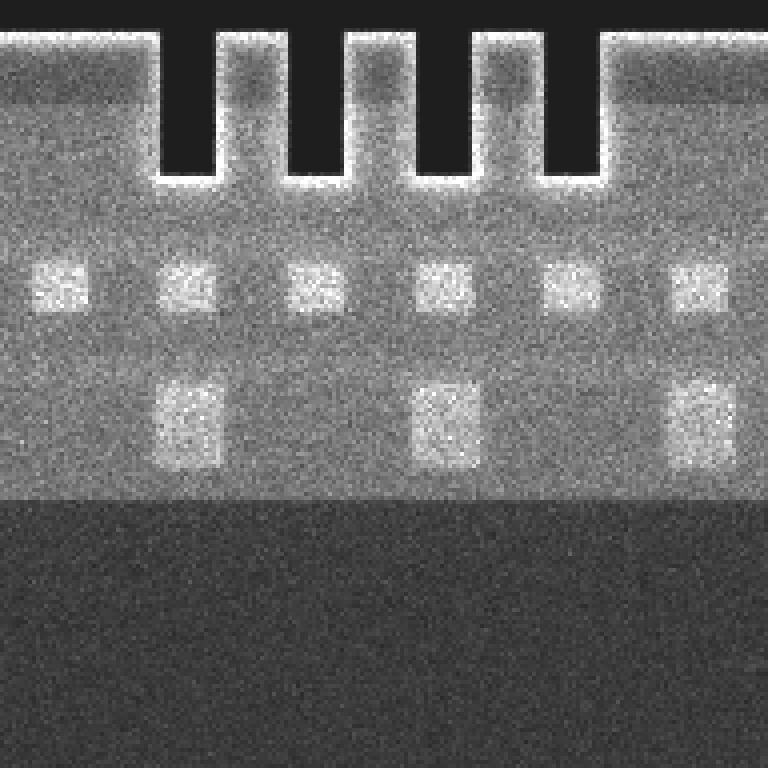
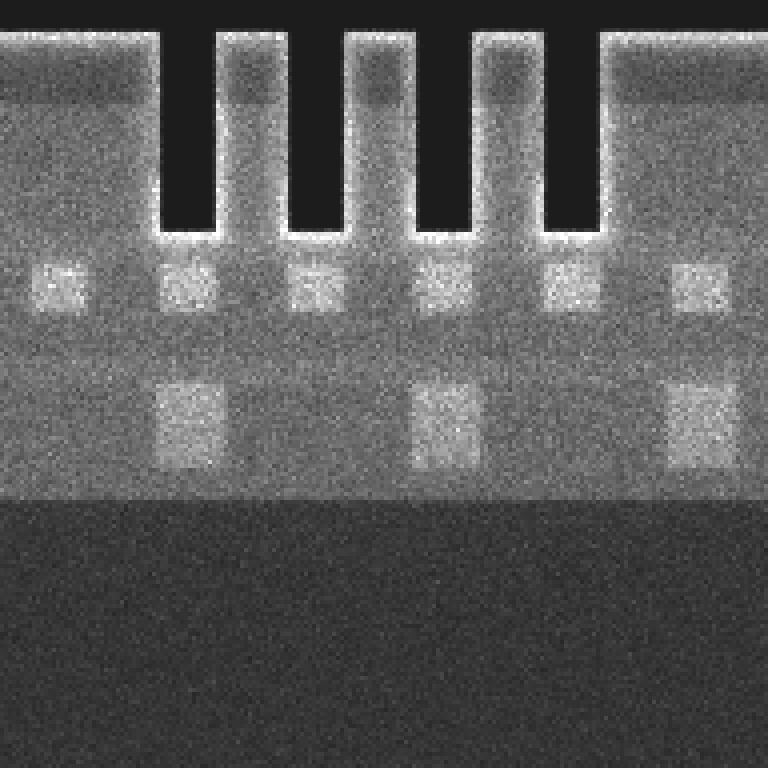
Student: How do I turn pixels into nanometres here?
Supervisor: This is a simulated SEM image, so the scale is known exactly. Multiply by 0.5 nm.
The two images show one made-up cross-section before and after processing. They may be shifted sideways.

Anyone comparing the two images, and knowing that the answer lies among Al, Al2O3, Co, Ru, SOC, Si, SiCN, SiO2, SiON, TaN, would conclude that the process removed SiO2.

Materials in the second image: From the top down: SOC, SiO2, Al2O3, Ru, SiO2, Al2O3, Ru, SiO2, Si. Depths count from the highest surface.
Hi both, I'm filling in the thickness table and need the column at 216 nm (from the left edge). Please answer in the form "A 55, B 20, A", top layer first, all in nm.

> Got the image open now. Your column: empty 100, Al2O3 16, Ru 24, SiO2 22, Al2O3 14, Ru 42, SiO2 16, Si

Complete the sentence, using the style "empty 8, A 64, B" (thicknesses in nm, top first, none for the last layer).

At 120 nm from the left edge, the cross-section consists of SOC 36, SiO2 64, Al2O3 16, SiO2 46, Al2O3 14, SiO2 58, Si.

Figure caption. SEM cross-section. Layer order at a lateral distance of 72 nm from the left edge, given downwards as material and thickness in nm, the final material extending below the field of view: SOC 36, SiO2 64, Al2O3 16, SiO2 46, Al2O3 14, SiO2 58, Si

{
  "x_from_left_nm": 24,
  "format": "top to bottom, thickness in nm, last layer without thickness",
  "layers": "SOC 36, SiO2 64, Al2O3 16, Ru 24, SiO2 22, Al2O3 14, SiO2 58, Si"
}